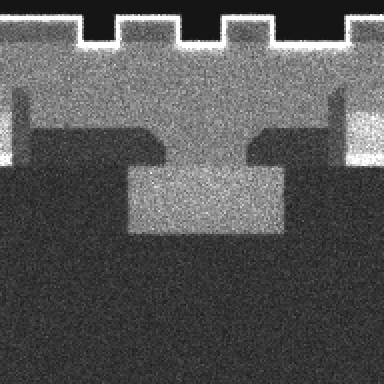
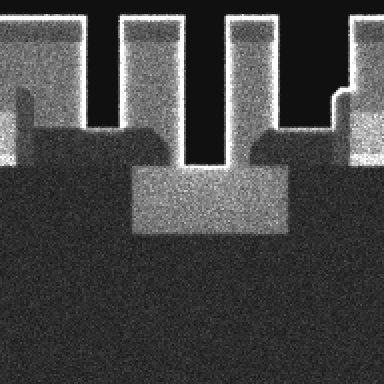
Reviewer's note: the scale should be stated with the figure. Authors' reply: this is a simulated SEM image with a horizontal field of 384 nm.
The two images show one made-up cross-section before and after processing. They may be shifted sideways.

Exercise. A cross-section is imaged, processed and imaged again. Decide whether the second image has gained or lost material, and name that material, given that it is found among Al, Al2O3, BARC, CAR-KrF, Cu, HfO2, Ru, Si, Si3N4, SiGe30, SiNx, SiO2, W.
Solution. removed: SiO2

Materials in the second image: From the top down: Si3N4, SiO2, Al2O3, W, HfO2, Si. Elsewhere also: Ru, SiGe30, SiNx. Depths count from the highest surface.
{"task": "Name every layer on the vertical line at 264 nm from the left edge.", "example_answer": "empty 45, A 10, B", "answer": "Si3N4 26, SiO2 90, SiGe30 34, Ru 68, Si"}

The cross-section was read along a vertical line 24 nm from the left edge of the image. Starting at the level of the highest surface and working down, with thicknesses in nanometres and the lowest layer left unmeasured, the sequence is Si3N4 26, SiO2 46, SiNx 78, Si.